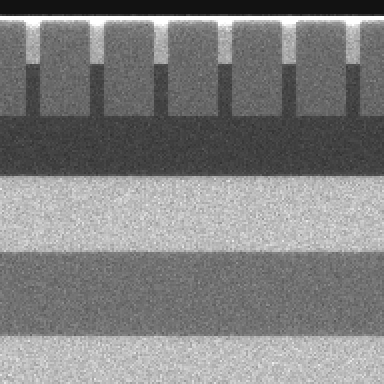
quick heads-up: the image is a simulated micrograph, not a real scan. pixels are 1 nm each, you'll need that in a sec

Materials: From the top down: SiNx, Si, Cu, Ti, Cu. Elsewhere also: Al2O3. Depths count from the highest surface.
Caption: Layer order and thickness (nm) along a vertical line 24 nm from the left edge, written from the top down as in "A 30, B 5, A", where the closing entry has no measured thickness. SiNx 100, Si 60, Cu 76, Ti 84, Cu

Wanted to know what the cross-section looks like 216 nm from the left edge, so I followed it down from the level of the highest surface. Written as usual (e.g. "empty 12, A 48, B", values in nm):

SiNx 100, Si 60, Cu 76, Ti 84, Cu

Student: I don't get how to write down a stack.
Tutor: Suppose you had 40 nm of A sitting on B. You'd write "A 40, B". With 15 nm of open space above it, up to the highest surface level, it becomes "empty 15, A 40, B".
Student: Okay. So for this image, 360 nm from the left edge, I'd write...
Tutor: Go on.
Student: SiNx 100, Si 60, Cu 76, Ti 84, Cu